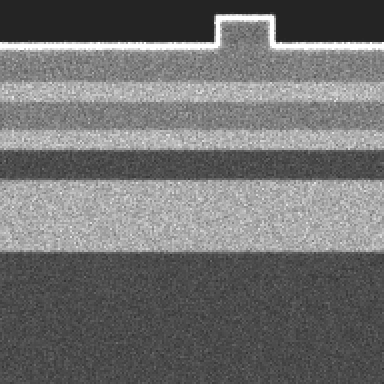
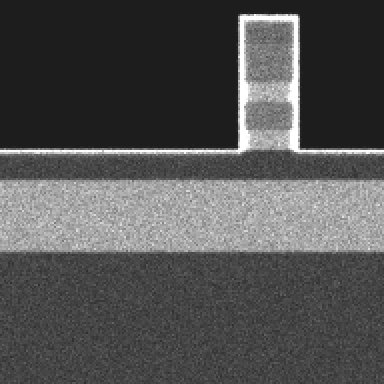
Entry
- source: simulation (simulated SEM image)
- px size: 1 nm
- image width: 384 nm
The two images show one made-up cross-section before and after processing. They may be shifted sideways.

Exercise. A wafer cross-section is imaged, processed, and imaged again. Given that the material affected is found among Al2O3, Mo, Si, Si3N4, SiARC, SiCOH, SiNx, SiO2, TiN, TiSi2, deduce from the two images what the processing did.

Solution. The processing removed Al2O3 and Si3N4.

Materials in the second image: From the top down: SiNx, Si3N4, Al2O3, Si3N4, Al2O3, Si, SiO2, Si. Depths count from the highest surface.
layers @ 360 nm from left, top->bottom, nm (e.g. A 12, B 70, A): empty 134, Si 30, SiO2 72, Si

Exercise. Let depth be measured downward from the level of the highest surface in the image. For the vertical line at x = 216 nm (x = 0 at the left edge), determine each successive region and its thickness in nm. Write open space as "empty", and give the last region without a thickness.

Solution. empty 134, Si 30, SiO2 72, Si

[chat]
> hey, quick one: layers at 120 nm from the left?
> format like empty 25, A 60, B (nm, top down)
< empty 134, Si 30, SiO2 72, Si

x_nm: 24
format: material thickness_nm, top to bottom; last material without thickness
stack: empty 134, Si 30, SiO2 72, Si